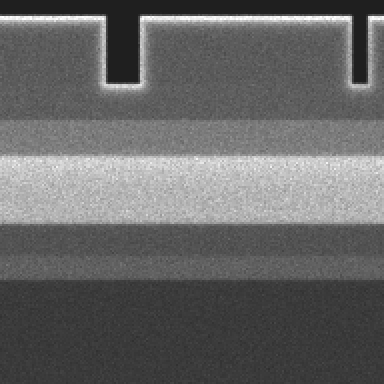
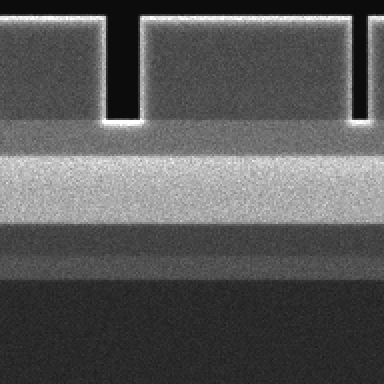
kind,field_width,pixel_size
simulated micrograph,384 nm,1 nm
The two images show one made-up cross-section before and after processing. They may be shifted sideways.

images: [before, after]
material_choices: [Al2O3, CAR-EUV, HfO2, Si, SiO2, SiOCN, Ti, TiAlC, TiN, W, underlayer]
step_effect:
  removed: underlayer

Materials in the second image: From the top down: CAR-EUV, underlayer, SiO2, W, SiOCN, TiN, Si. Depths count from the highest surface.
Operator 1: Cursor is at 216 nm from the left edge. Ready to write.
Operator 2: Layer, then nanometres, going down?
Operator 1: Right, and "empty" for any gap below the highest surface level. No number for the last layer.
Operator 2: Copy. CAR-EUV 68, underlayer 36, SiO2 36, W 68, SiOCN 32, TiN 24, Si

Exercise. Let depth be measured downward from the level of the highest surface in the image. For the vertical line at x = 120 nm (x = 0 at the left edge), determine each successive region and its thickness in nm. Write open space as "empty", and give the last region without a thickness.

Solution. empty 104, SiO2 36, W 68, SiOCN 32, TiN 24, Si